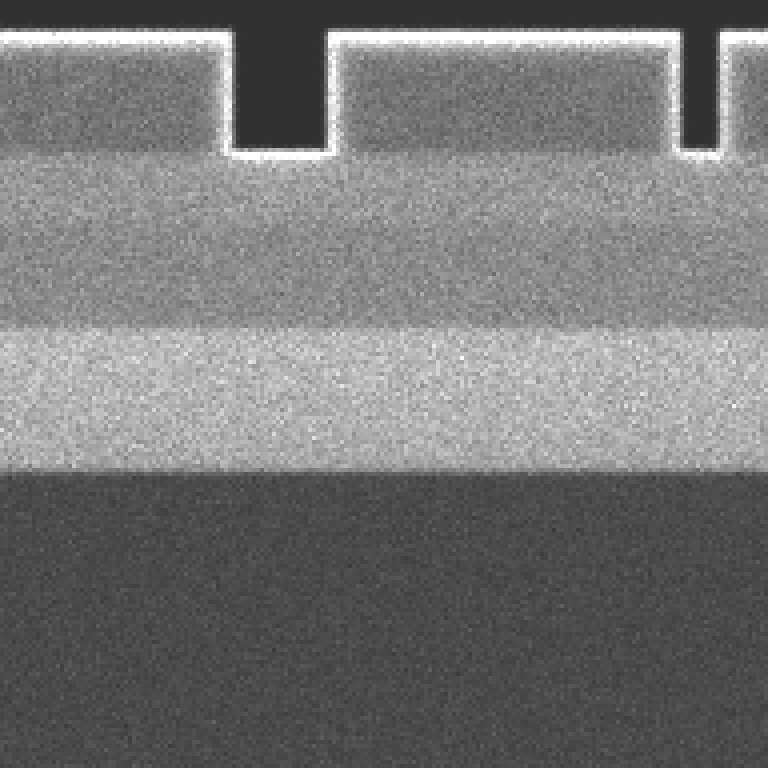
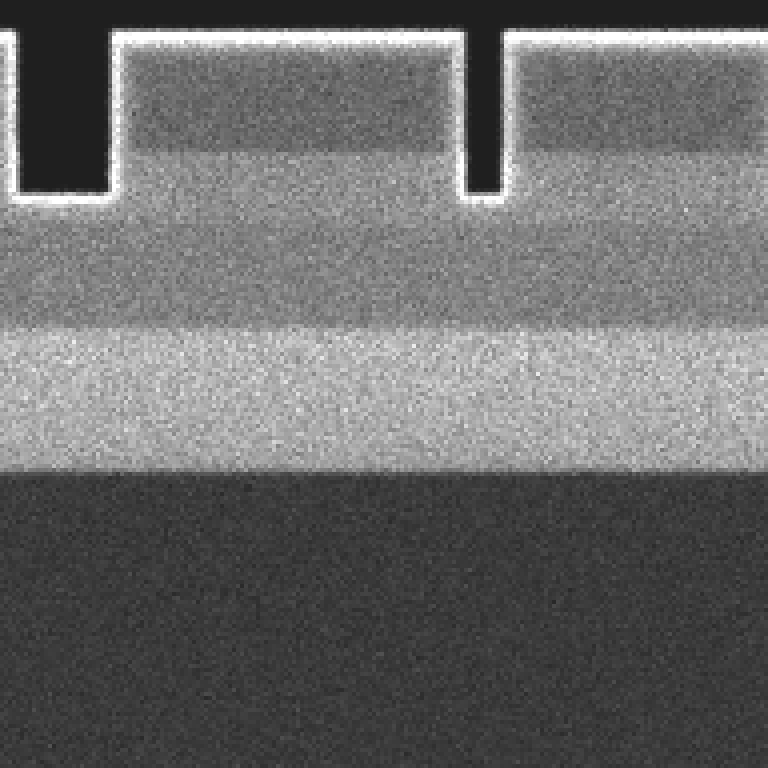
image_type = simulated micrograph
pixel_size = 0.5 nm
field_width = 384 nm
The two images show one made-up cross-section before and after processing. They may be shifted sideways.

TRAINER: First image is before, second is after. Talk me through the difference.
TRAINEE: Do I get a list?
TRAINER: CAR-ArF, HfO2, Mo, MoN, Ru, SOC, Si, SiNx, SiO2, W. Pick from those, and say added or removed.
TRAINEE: removed: Ru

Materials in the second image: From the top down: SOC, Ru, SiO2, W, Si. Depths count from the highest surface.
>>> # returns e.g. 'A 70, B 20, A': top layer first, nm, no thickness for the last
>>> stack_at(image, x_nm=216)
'SOC 60, Ru 36, SiO2 52, W 72, Si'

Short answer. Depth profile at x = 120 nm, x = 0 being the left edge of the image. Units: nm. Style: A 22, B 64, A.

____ SOC 60, Ru 36, SiO2 52, W 72, Si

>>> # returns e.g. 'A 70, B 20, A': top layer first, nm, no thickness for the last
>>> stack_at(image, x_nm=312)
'SOC 60, Ru 36, SiO2 52, W 72, Si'